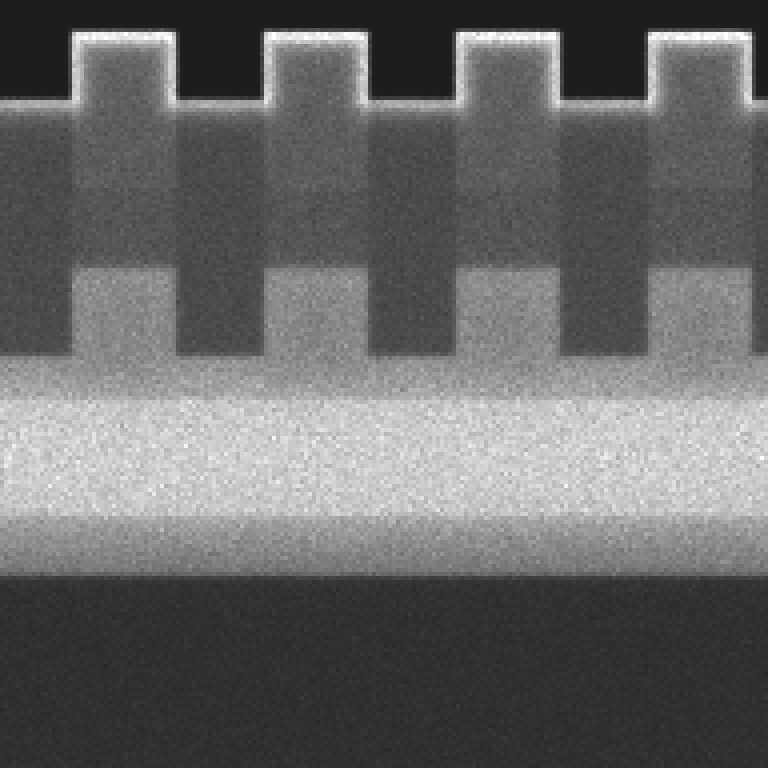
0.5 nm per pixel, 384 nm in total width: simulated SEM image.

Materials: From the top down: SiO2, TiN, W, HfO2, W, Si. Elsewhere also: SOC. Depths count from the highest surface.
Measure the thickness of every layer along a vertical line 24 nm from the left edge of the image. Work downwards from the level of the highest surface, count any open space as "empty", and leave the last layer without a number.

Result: empty 34, SOC 128, W 22, HfO2 58, W 30, Si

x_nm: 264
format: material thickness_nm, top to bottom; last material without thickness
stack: SiO2 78, TiN 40, W 66, HfO2 58, W 30, Si